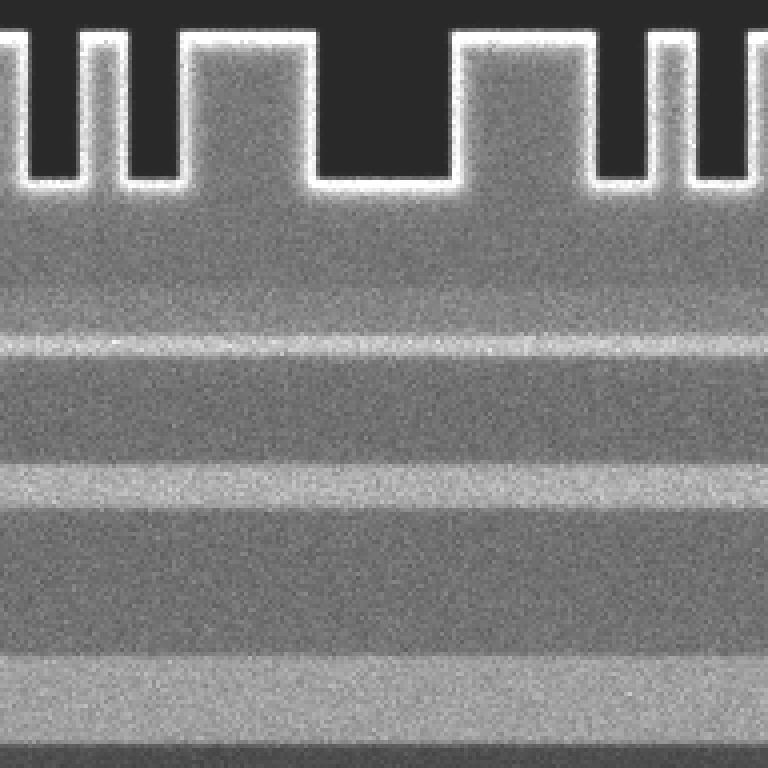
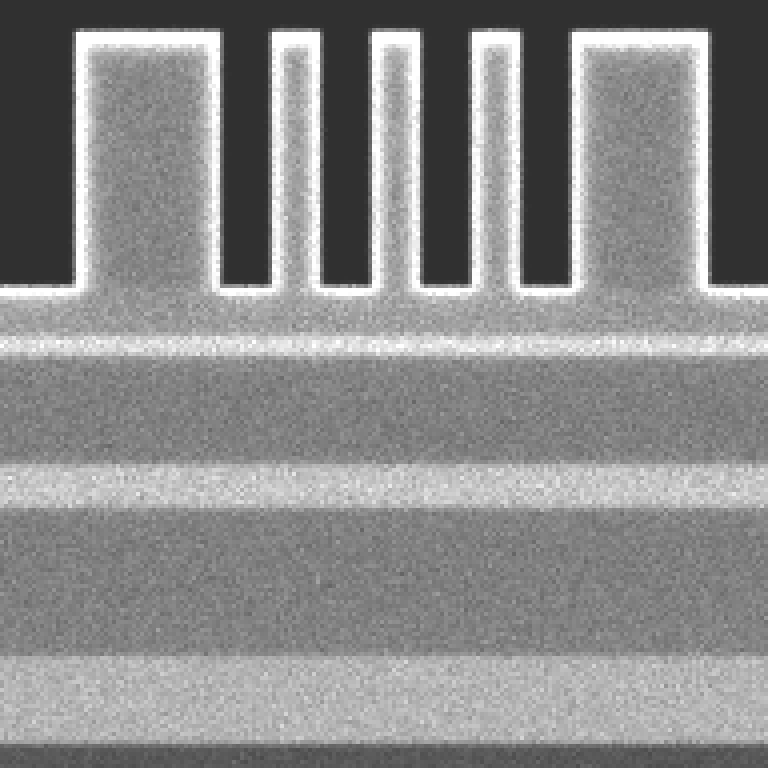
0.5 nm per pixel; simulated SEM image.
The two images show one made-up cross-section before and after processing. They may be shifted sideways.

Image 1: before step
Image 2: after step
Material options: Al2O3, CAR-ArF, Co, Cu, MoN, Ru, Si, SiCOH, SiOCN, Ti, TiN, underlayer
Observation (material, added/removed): underlayer, removed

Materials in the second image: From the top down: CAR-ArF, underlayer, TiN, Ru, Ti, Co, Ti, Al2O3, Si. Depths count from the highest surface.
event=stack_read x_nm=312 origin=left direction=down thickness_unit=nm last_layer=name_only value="CAR-ArF 74, underlayer 54, TiN 24, Ru 10, Ti 54, Co 22, Ti 74, Al2O3 44, Si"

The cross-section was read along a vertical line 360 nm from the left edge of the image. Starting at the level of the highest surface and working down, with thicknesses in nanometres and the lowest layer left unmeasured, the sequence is empty 128, TiN 24, Ru 10, Ti 54, Co 22, Ti 74, Al2O3 44, Si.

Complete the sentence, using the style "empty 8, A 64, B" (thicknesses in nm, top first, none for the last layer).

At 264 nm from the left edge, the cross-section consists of empty 128, TiN 24, Ru 10, Ti 54, Co 22, Ti 74, Al2O3 44, Si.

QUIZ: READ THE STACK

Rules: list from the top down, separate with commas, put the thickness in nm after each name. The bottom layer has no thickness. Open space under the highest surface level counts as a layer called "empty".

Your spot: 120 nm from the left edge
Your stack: empty 128, TiN 24, Ru 10, Ti 54, Co 22, Ti 74, Al2O3 44, Si